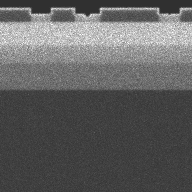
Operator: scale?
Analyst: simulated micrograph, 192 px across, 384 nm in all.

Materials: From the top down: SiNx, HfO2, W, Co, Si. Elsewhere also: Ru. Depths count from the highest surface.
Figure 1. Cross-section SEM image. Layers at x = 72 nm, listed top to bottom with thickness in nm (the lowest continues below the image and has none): empty 12, Ru 16, HfO2 46, W 36, Co 54, Si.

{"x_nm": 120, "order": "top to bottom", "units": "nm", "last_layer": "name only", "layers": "SiNx 28, HfO2 46, W 36, Co 54, Si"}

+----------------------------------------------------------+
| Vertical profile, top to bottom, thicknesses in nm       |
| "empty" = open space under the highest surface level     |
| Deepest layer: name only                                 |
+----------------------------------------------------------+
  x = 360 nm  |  SiNx 28, HfO2 46, W 36, Co 54, Si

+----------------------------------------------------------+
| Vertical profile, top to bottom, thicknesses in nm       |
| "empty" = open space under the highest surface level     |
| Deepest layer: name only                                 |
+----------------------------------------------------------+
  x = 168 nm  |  empty 14, Ru 14, HfO2 46, W 36, Co 54, Si